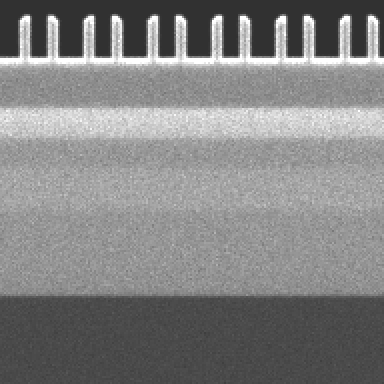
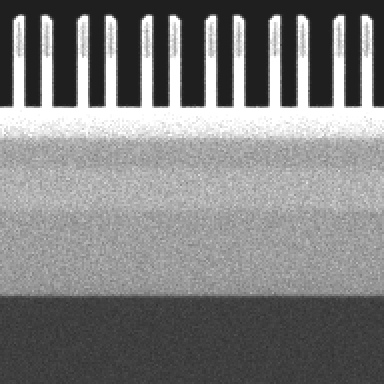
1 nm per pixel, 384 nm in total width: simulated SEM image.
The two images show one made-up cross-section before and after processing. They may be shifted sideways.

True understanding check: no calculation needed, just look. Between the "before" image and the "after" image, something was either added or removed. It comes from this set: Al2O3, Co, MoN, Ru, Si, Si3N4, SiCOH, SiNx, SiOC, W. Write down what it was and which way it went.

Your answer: Al2O3 (removed)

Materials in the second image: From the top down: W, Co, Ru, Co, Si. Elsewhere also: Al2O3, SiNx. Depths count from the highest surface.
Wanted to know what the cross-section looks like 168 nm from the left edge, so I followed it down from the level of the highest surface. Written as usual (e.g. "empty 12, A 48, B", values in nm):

empty 92, W 30, Co 30, Ru 42, Co 86, Si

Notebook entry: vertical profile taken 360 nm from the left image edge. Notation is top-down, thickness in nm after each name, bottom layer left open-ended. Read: empty 92, W 30, Co 30, Ru 42, Co 86, Si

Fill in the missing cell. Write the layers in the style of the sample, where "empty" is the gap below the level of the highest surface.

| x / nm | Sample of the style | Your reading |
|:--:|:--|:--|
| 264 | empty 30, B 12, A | empty 92, W 30, Co 30, Ru 42, Co 86, Si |